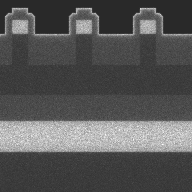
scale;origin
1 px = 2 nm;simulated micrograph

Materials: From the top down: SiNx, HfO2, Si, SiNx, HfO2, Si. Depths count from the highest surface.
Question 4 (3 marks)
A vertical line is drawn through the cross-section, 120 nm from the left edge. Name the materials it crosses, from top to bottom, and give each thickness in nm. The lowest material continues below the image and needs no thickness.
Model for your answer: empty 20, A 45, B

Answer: empty 52, SiNx 62, Si 60, SiNx 52, HfO2 62, Si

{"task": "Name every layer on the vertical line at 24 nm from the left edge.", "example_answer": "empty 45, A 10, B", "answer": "SiNx 24, HfO2 28, Si 122, SiNx 52, HfO2 62, Si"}